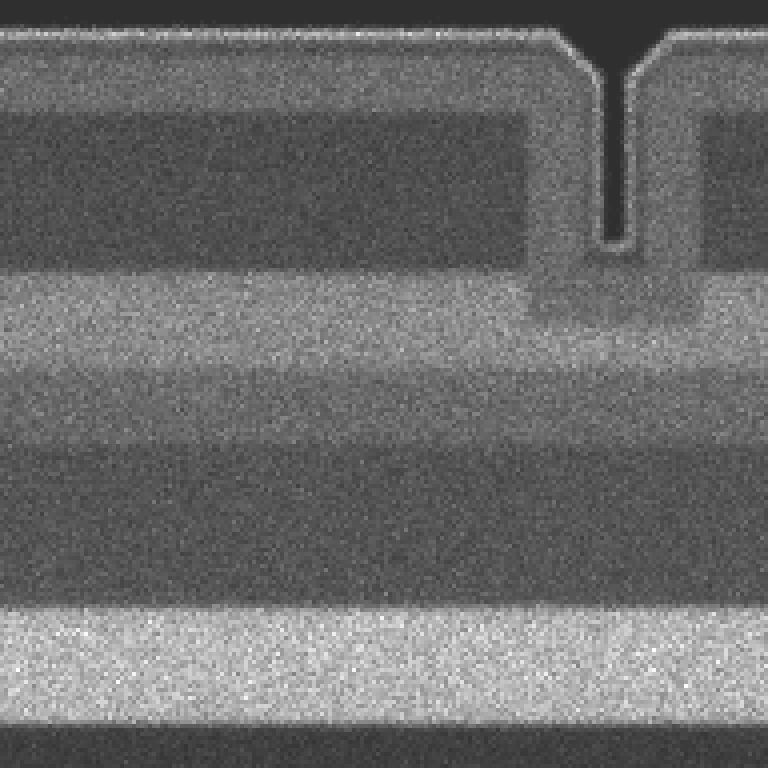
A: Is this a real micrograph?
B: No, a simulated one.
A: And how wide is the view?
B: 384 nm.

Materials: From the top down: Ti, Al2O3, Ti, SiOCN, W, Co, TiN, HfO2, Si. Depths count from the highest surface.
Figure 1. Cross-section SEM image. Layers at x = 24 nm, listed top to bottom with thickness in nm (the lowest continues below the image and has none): Ti 12, Al2O3 28, Ti 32, SiOCN 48, W 48, Co 38, TiN 82, HfO2 58, Si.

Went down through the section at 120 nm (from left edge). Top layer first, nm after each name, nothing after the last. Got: Ti 12, Al2O3 28, Ti 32, SiOCN 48, W 48, Co 38, TiN 82, HfO2 58, Si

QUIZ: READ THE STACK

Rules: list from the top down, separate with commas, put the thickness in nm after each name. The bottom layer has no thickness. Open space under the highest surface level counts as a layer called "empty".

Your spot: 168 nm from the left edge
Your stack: Ti 12, Al2O3 28, Ti 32, SiOCN 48, W 48, Co 38, TiN 82, HfO2 58, Si